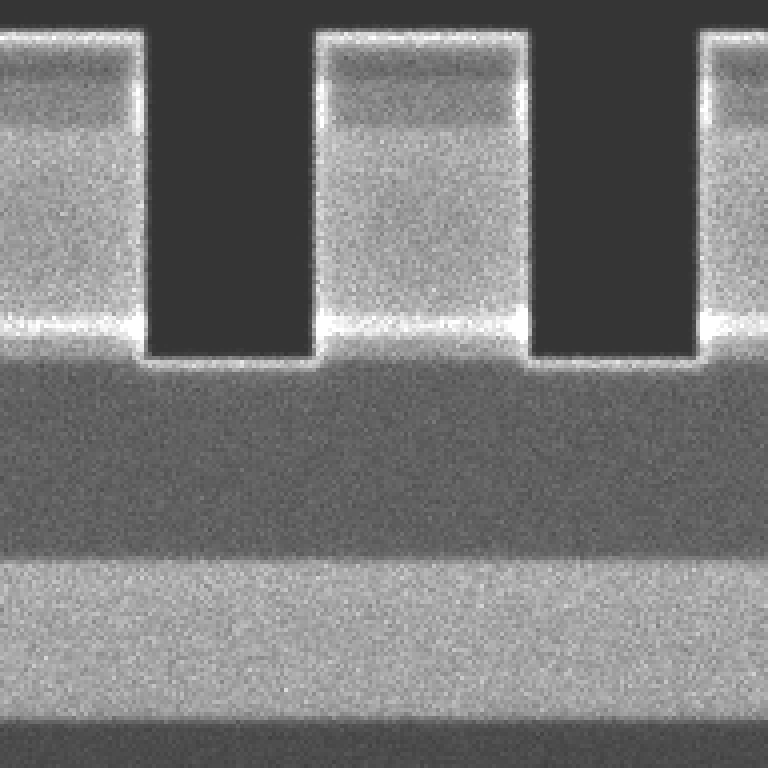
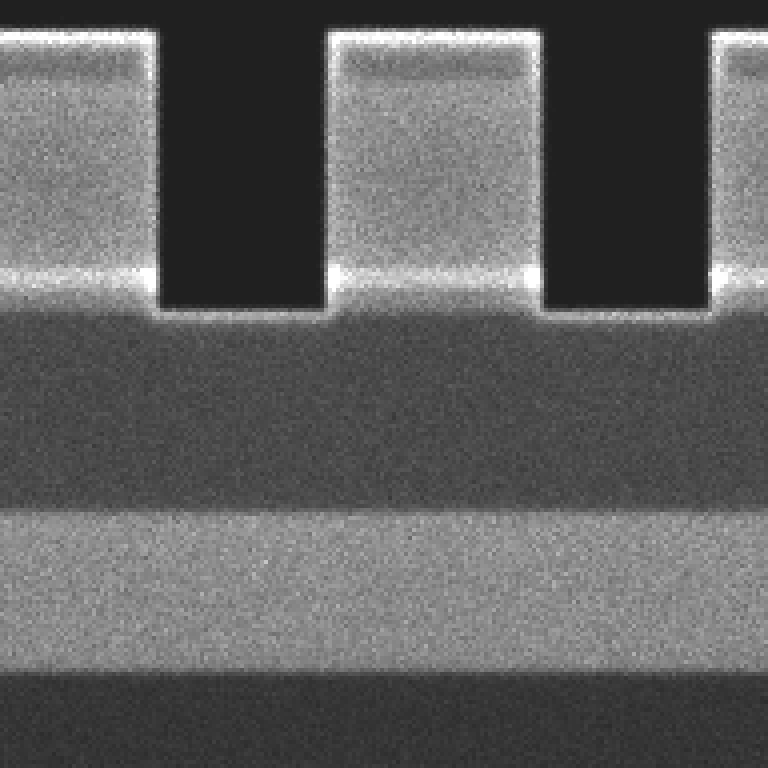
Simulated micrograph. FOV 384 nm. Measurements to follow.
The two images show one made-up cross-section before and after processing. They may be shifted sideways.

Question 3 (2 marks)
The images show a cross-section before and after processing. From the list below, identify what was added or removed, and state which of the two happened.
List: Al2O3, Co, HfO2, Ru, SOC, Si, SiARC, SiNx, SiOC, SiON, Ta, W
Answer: SOC was removed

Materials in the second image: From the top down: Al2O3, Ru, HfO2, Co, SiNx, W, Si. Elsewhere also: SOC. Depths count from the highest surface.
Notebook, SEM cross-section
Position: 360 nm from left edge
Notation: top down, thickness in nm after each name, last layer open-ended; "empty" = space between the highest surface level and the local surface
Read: Al2O3 24, Ru 94, HfO2 10, Co 12, SiNx 100, W 80, Si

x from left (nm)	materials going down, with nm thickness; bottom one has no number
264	Al2O3 24, Ru 94, HfO2 10, Co 12, SiNx 100, W 80, Si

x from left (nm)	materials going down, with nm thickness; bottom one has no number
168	Al2O3 24, Ru 94, HfO2 10, Co 12, SiNx 100, W 80, Si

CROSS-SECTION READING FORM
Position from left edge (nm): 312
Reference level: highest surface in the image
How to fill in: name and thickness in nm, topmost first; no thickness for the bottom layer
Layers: empty 140, SiNx 100, W 80, Si